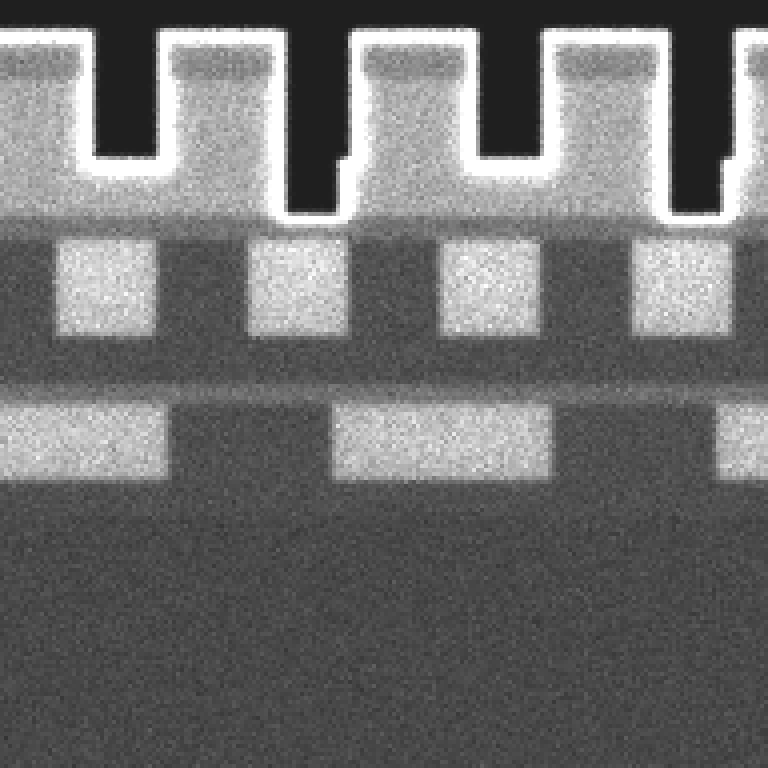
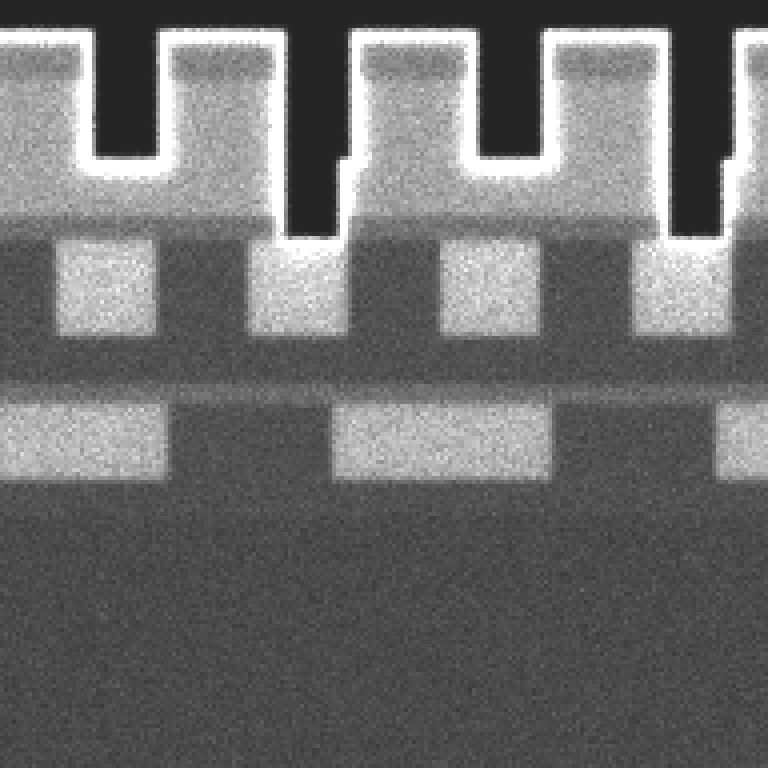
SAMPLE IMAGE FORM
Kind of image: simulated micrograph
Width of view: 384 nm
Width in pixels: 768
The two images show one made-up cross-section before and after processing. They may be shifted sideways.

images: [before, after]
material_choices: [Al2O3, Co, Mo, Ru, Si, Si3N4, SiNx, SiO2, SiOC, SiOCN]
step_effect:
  removed: SiNx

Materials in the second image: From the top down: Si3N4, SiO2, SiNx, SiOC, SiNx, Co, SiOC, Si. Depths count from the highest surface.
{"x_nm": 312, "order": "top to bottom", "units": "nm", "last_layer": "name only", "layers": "Si3N4 24, SiO2 68, SiNx 12, SiOC 72, SiNx 10, SiOC 56, Si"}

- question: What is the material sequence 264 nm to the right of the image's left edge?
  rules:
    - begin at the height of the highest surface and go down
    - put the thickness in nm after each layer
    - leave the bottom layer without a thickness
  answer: empty 64, SiO2 28, SiNx 12, Co 48, SiOC 24, SiNx 10, Co 38, SiOC 18, Si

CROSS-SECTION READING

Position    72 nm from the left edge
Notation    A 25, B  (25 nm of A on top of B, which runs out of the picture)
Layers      empty 64, SiO2 28, SiNx 12, Co 48, SiOC 24, SiNx 10, Co 38, SiOC 18, Si